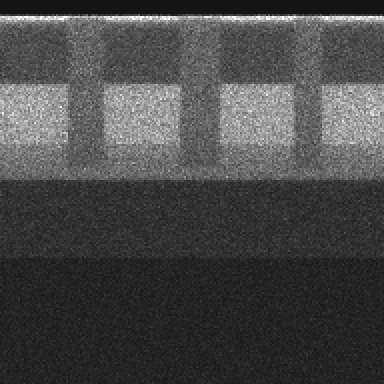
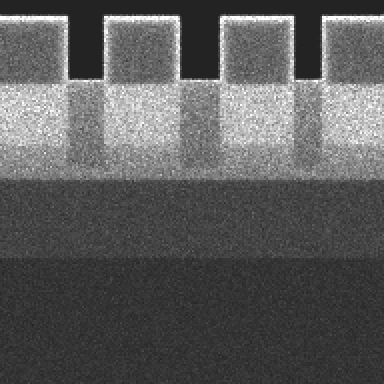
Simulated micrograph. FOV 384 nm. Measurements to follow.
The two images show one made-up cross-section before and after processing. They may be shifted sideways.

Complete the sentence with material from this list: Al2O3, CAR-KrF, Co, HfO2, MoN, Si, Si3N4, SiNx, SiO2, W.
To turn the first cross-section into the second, Co must be removed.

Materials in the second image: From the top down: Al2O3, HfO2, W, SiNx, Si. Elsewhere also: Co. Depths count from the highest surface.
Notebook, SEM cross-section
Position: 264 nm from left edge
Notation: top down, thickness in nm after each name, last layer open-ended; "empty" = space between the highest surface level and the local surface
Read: Al2O3 68, HfO2 60, W 36, SiNx 78, Si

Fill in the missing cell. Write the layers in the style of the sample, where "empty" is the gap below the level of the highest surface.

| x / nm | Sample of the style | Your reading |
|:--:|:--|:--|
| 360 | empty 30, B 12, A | Al2O3 68, HfO2 60, W 36, SiNx 78, Si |